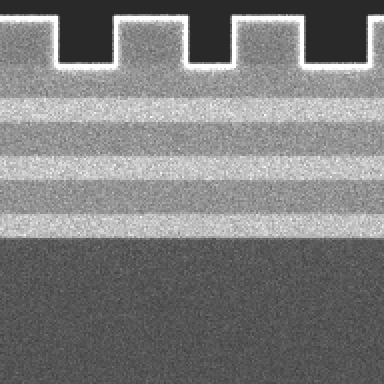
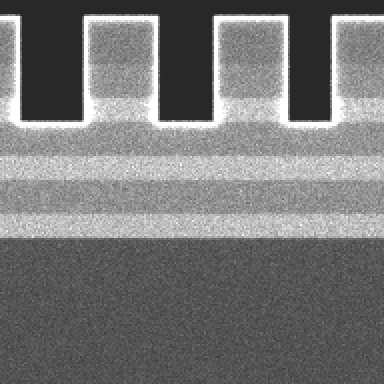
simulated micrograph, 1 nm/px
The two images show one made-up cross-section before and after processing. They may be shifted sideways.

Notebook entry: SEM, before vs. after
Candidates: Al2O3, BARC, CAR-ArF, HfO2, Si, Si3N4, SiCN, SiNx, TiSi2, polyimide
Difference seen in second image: Al2O3 and Si3N4 removed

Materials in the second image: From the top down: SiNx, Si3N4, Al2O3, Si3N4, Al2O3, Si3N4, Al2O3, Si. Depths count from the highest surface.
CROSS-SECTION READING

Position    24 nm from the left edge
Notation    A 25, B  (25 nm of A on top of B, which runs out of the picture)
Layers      empty 106, Si3N4 34, Al2O3 24, Si3N4 34, Al2O3 24, Si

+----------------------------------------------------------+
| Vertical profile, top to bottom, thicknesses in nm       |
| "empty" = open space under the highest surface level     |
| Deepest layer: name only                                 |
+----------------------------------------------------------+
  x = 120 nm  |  SiNx 48, Si3N4 34, Al2O3 24, Si3N4 34, Al2O3 24, Si3N4 34, Al2O3 24, Si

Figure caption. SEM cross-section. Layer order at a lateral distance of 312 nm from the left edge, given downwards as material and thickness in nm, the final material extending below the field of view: empty 106, Si3N4 34, Al2O3 24, Si3N4 34, Al2O3 24, Si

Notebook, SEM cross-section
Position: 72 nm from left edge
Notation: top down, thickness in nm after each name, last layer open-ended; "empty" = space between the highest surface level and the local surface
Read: empty 106, Si3N4 34, Al2O3 24, Si3N4 34, Al2O3 24, Si